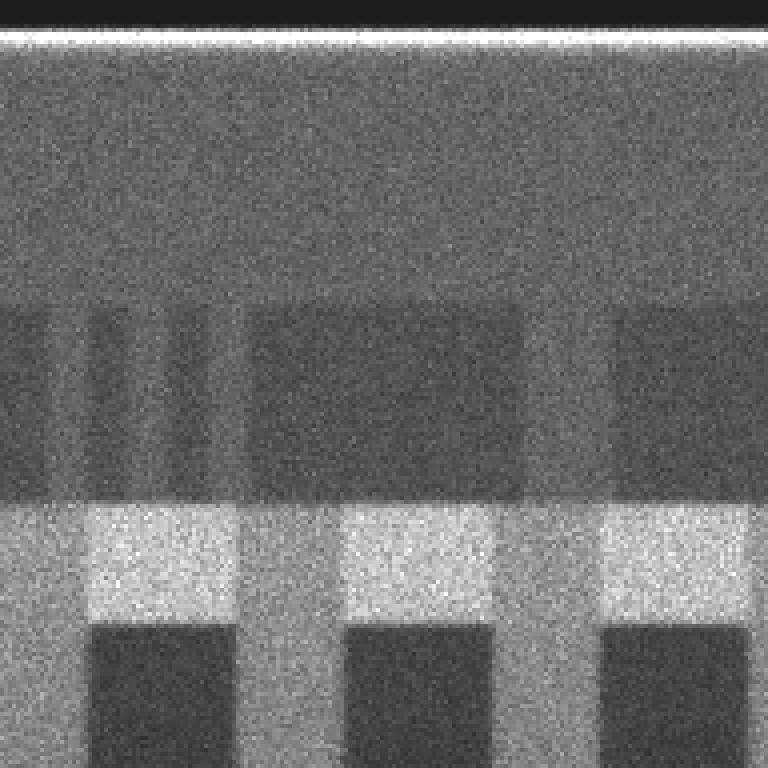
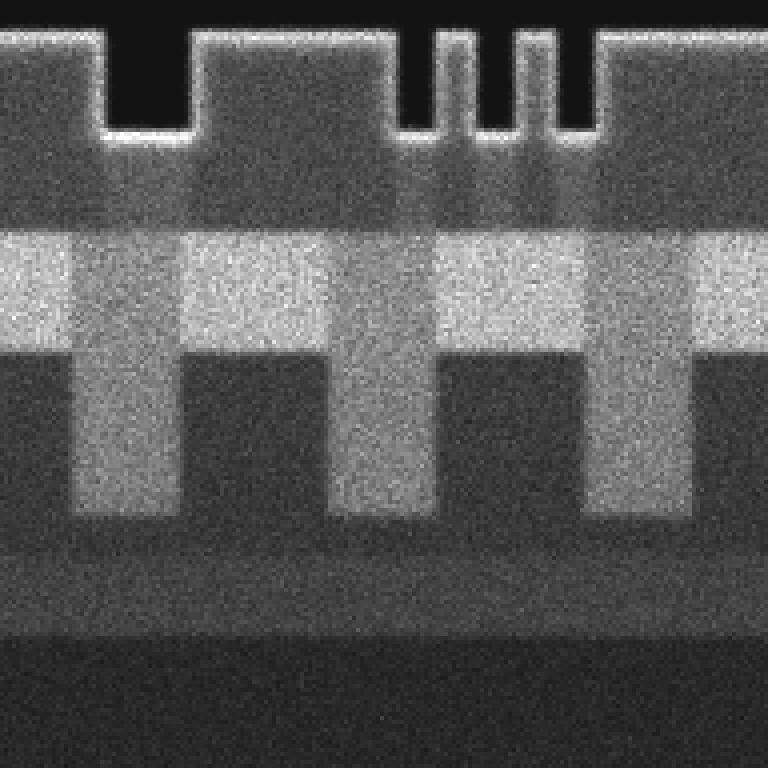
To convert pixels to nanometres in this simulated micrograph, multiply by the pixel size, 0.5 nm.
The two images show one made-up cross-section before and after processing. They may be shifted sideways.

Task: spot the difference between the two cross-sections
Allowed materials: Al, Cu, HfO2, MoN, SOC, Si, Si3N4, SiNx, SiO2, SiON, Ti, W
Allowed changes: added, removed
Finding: removed SiO2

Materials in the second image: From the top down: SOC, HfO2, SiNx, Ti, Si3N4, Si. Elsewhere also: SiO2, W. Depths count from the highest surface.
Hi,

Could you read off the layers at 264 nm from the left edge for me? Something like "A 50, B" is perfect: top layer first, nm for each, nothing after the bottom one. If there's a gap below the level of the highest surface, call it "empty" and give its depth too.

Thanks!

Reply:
SOC 100, HfO2 60, SiNx 52, Ti 50, Si3N4 40, Si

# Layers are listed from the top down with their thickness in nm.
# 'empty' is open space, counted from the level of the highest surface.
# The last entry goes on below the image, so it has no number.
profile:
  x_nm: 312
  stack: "SOC 100, W 142, Ti 20, Si3N4 40, Si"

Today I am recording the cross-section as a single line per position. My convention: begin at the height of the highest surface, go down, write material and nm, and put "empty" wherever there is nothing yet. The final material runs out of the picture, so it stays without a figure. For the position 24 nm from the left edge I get SOC 100, HfO2 60, SiNx 52, Ti 50, Si3N4 40, Si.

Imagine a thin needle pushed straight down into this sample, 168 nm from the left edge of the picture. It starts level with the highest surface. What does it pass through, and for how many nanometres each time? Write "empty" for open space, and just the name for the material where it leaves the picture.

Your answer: SOC 100, W 142, Ti 20, Si3N4 40, Si